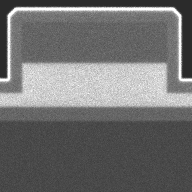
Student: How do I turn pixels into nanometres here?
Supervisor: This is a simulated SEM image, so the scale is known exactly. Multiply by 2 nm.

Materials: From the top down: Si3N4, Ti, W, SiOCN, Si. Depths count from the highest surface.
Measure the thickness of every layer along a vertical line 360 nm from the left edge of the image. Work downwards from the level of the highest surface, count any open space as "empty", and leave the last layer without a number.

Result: empty 14, Si3N4 156, W 28, SiOCN 28, Si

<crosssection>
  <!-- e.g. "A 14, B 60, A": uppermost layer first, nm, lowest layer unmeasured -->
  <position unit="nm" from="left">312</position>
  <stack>Si3N4 28, Ti 82, W 88, SiOCN 28, Si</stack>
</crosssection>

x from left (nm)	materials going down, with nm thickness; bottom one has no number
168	Si3N4 28, Ti 82, W 88, SiOCN 28, Si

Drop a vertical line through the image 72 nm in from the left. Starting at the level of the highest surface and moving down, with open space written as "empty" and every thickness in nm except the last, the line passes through Si3N4 28, Ti 82, W 88, SiOCN 28, Si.